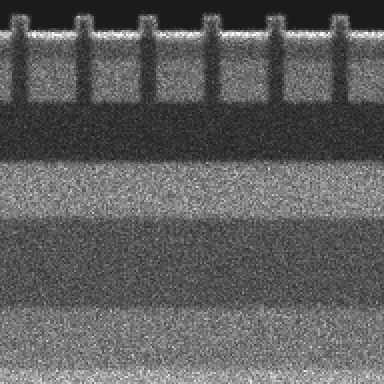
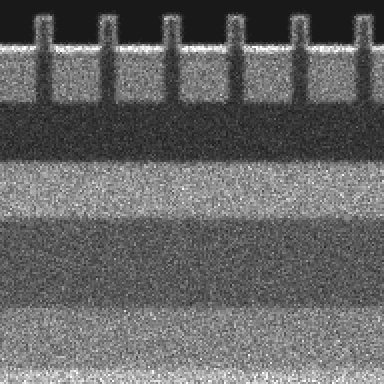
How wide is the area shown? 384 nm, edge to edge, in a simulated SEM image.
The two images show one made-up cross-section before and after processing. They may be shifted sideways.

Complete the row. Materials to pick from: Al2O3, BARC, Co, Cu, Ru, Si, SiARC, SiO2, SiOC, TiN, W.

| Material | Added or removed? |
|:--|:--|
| SiARC | removed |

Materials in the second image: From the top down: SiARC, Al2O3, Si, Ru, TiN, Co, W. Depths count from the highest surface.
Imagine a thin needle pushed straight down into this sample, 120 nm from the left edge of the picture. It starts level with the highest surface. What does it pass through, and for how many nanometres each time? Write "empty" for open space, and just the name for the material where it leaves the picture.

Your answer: empty 30, SiARC 14, Al2O3 42, Si 60, Ru 56, TiN 90, Co 62, W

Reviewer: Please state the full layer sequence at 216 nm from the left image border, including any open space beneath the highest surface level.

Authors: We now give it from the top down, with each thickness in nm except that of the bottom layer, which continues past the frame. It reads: empty 30, SiARC 14, Al2O3 42, Si 60, Ru 56, TiN 90, Co 62, W